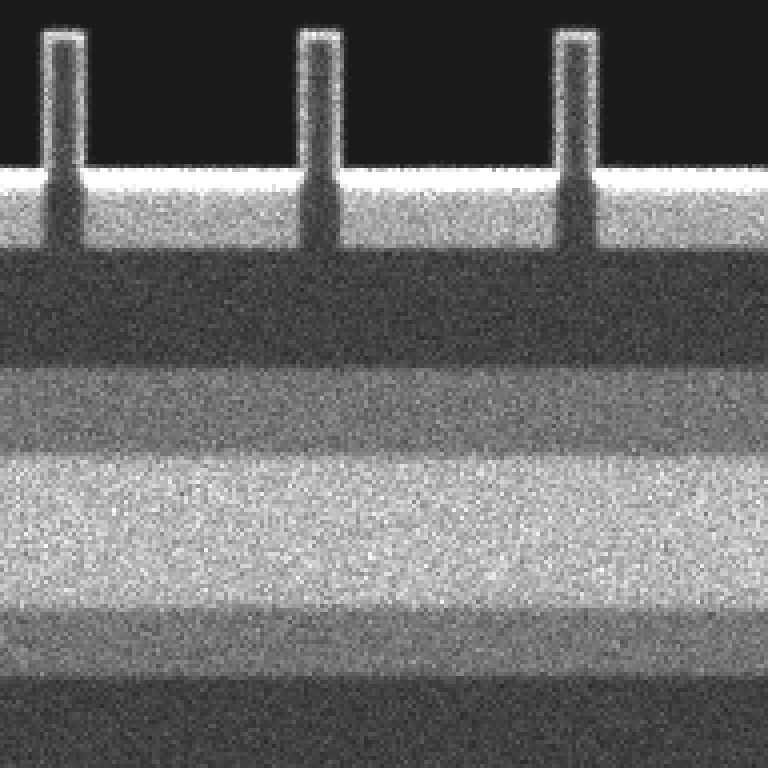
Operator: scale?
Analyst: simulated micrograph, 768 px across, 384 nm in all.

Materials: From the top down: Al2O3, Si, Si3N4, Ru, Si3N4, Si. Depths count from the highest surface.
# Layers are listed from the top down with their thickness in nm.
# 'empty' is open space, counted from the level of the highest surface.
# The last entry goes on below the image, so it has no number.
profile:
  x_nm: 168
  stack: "Si 168, Si3N4 44, Ru 76, Si3N4 34, Si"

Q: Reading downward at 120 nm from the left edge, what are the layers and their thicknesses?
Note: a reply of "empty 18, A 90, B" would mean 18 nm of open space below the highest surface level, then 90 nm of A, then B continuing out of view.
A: empty 70, Al2O3 38, Si 60, Si3N4 44, Ru 76, Si3N4 34, Si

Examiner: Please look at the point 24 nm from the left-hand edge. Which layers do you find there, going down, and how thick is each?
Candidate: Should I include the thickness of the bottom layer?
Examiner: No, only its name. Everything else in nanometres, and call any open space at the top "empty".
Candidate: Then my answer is Si 168, Si3N4 44, Ru 76, Si3N4 34, Si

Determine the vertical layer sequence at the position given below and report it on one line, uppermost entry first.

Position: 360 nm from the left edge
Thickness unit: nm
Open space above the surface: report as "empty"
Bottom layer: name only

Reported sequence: empty 70, Al2O3 38, Si 60, Si3N4 44, Ru 76, Si3N4 34, Si